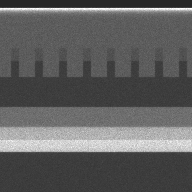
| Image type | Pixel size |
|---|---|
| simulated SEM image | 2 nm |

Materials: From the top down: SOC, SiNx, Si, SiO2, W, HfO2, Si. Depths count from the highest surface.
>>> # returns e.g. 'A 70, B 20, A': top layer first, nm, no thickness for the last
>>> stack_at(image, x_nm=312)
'SOC 80, SiNx 26, Si 92, SiO2 40, W 26, HfO2 24, Si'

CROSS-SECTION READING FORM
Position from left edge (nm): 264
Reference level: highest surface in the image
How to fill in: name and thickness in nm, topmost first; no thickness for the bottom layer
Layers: SOC 80, SiNx 26, Si 92, SiO2 40, W 26, HfO2 24, Si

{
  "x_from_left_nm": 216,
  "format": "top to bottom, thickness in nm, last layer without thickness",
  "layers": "SOC 80, SiNx 26, Si 92, SiO2 40, W 26, HfO2 24, Si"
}